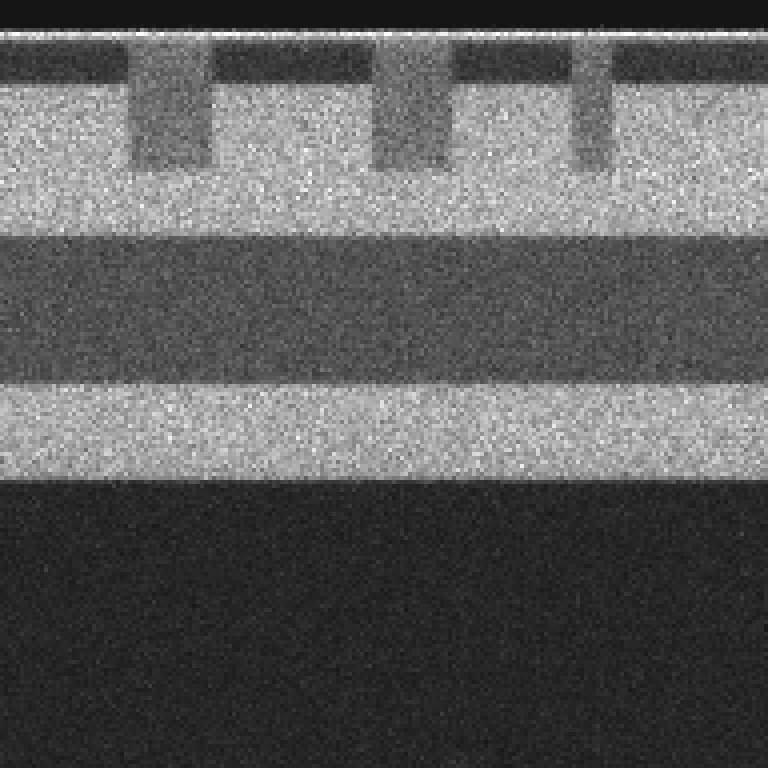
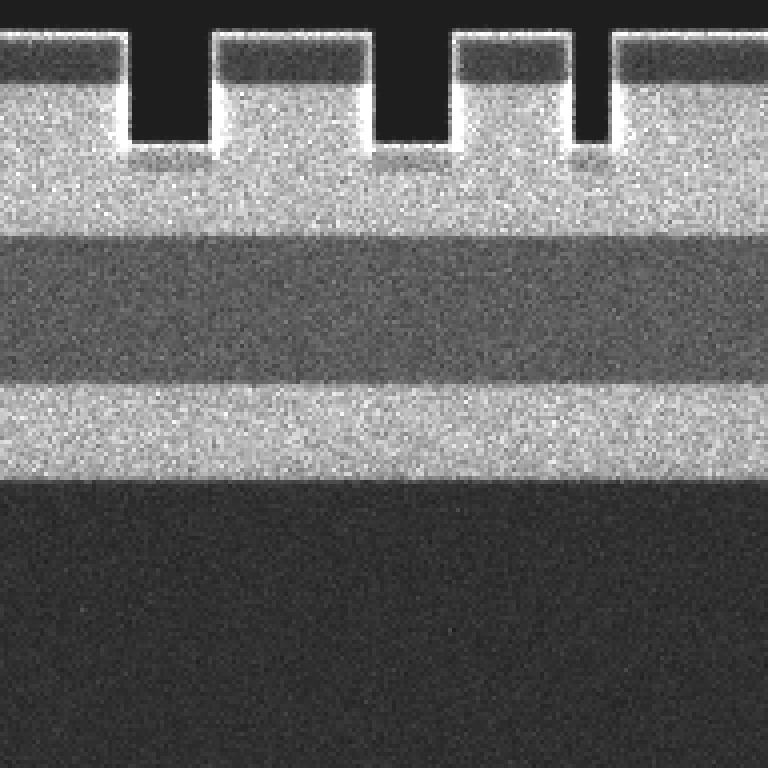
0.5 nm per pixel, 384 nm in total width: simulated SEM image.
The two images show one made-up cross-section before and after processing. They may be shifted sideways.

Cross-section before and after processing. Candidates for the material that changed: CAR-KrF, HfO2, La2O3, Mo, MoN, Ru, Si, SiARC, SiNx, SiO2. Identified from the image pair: Ru (removed).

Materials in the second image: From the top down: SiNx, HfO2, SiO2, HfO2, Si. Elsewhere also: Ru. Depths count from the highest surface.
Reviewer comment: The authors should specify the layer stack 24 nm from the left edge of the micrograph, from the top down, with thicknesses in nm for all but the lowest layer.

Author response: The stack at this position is SiNx 26, HfO2 76, SiO2 74, HfO2 48, Si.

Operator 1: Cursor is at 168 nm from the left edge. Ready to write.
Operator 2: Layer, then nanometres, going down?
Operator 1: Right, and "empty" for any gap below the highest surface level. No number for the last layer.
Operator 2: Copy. SiNx 26, HfO2 76, SiO2 74, HfO2 48, Si